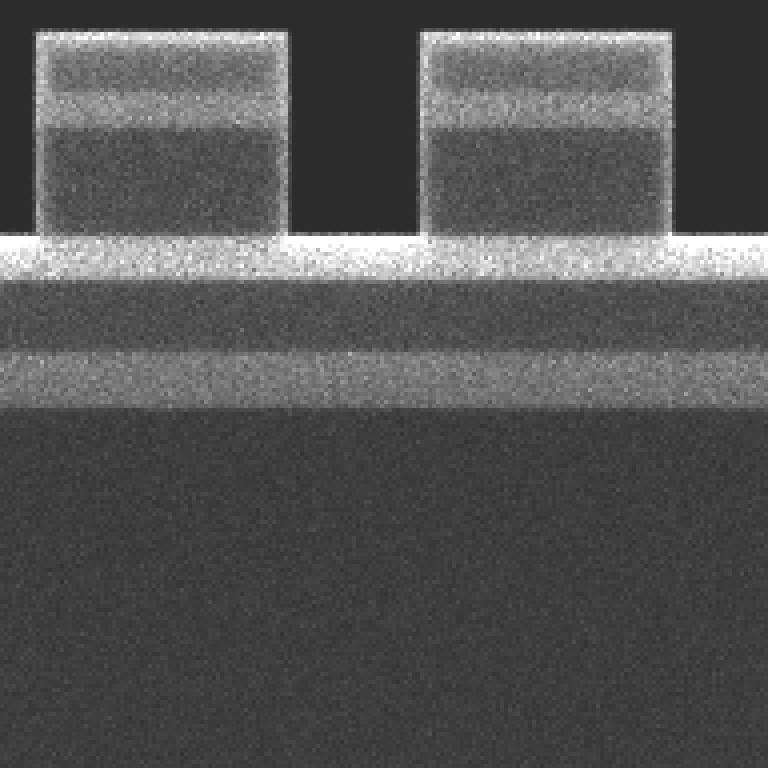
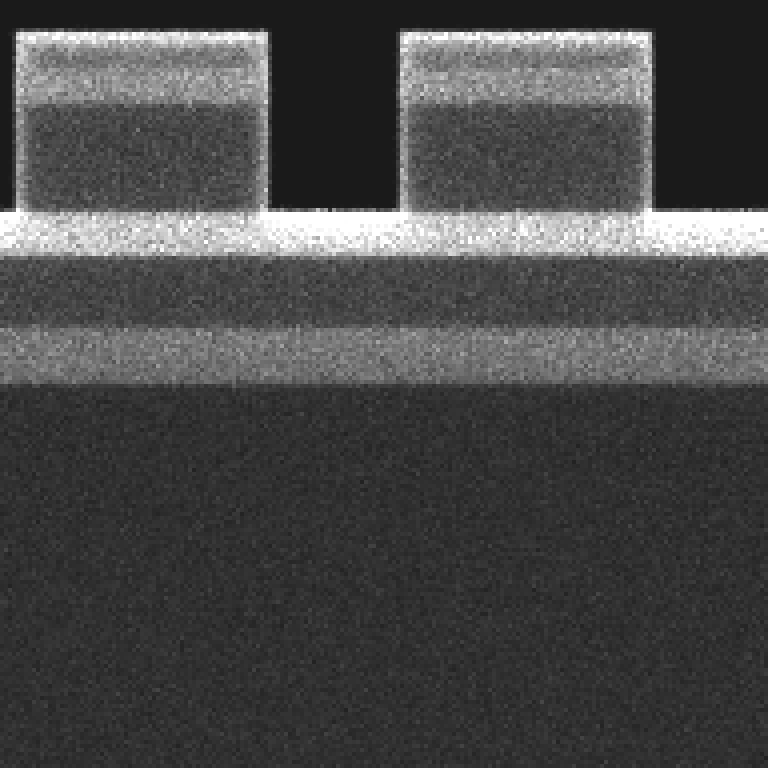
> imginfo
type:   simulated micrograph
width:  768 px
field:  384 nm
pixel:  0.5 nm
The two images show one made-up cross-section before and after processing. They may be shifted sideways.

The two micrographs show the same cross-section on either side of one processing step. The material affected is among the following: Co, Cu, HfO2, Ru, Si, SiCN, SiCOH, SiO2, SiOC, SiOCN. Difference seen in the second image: SiO2 removed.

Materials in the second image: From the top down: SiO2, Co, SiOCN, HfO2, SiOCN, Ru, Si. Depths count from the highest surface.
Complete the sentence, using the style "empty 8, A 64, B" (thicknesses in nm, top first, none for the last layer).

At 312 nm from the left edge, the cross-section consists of SiO2 18, Co 18, SiOCN 54, HfO2 22, SiOCN 36, Ru 28, Si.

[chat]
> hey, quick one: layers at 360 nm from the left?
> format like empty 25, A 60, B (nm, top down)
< empty 90, HfO2 22, SiOCN 36, Ru 28, Si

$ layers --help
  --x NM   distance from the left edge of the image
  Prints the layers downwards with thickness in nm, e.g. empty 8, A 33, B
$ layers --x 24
SiO2 18, Co 18, SiOCN 54, HfO2 22, SiOCN 36, Ru 28, Si